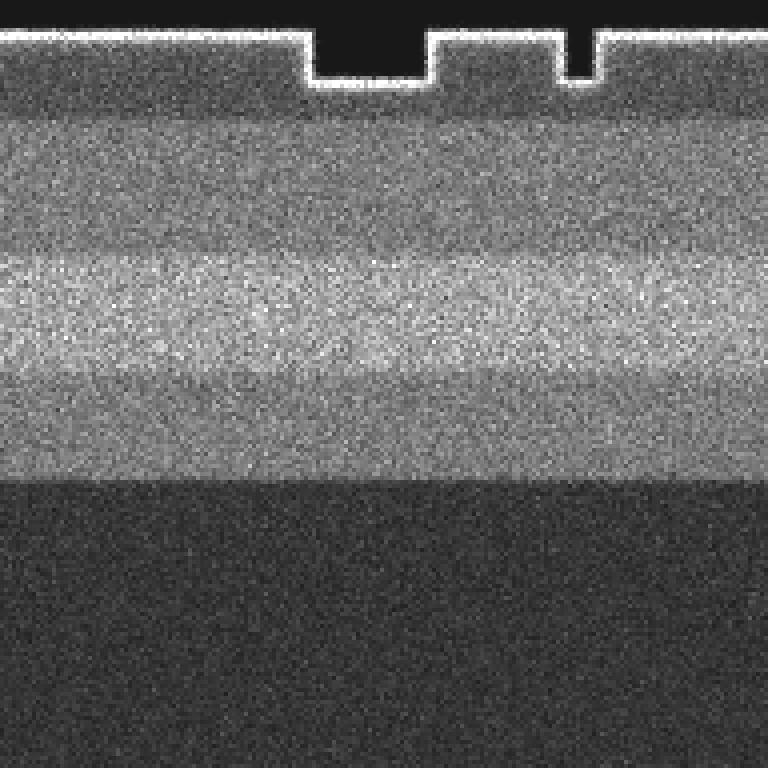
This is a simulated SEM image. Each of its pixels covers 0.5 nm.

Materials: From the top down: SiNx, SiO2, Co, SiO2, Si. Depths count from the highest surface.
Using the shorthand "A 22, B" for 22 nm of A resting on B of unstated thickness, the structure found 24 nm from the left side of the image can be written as SiNx 44, SiO2 68, Co 58, SiO2 54, Si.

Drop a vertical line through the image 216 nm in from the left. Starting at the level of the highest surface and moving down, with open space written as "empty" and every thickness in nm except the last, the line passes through SiNx 44, SiO2 68, Co 58, SiO2 54, Si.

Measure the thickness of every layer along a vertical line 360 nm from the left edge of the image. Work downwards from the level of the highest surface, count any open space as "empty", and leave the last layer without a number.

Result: SiNx 44, SiO2 68, Co 58, SiO2 54, Si